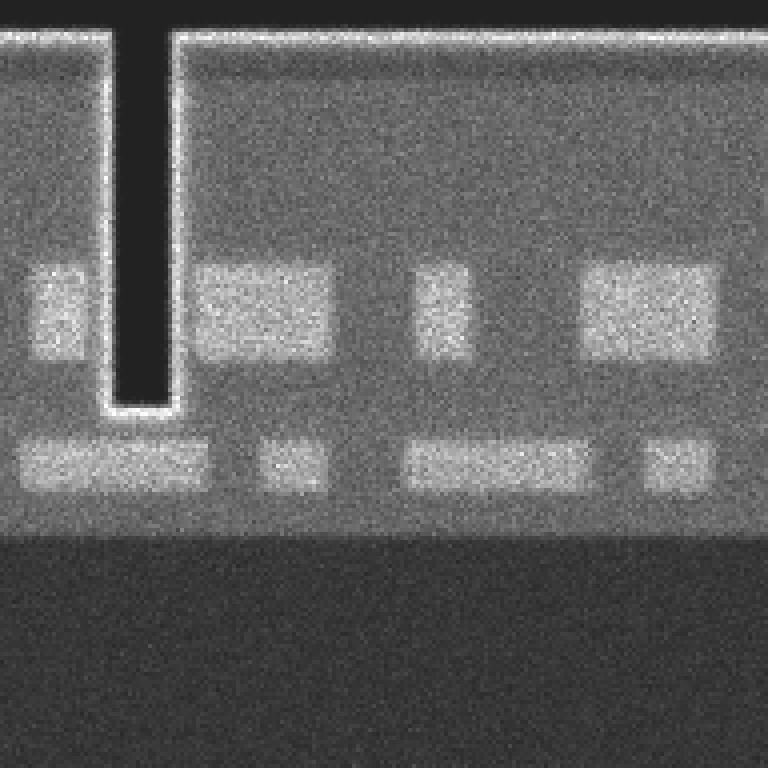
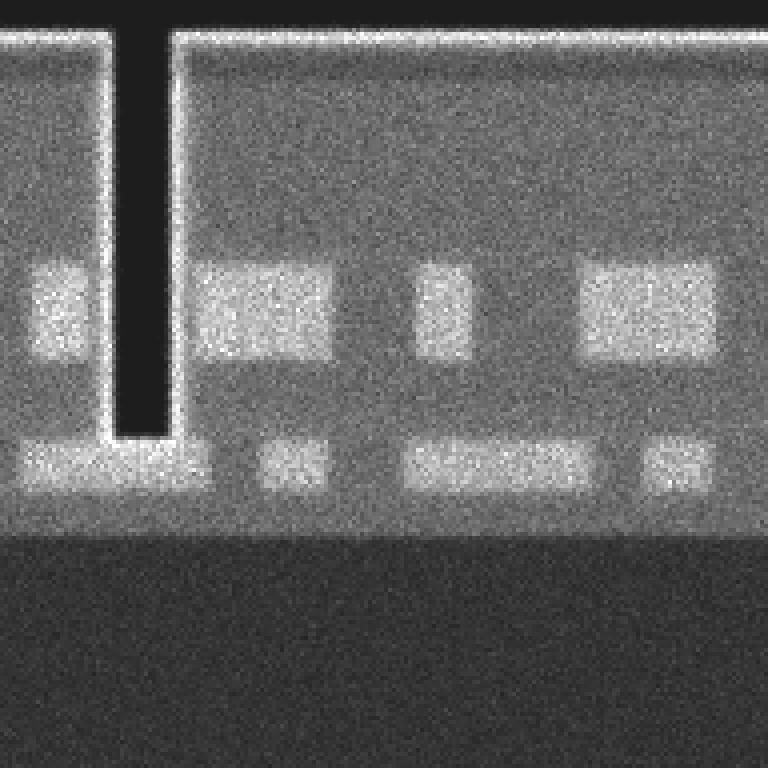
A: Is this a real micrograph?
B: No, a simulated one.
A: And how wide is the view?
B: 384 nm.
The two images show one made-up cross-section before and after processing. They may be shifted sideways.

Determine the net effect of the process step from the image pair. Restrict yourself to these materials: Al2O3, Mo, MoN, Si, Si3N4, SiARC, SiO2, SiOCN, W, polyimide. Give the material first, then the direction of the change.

Al2O3: removed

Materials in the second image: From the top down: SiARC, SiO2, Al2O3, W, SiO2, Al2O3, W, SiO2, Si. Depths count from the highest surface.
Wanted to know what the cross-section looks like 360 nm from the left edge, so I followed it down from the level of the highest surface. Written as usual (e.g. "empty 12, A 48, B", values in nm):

SiARC 24, SiO2 82, Al2O3 10, SiO2 72, Al2O3 16, SiO2 48, Si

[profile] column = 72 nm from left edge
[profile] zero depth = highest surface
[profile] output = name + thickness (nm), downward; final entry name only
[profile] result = empty 204, W 26, SiO2 22, Si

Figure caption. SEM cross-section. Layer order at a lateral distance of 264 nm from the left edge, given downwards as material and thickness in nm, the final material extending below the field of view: SiARC 24, SiO2 82, Al2O3 10, SiO2 72, Al2O3 16, W 26, SiO2 22, Si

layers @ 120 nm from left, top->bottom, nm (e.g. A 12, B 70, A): SiARC 24, SiO2 82, Al2O3 10, W 48, SiO2 24, Al2O3 16, SiO2 48, Si